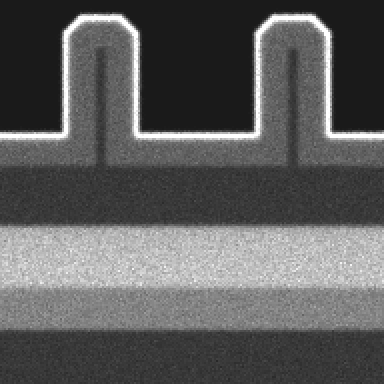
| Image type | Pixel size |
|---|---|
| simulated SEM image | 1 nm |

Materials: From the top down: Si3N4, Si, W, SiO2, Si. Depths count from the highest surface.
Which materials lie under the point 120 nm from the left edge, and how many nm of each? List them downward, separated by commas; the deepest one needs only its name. Si3N4 150, Si 60, W 62, SiO2 42, Si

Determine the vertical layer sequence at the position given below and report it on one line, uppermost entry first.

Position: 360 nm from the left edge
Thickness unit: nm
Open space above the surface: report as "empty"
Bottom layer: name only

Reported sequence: empty 118, Si3N4 32, Si 60, W 62, SiO2 42, Si